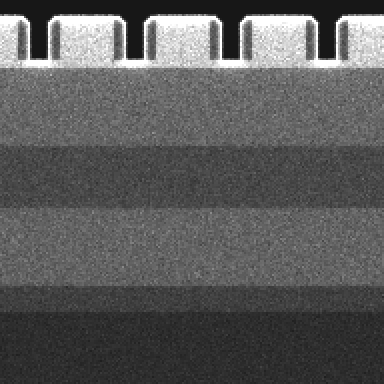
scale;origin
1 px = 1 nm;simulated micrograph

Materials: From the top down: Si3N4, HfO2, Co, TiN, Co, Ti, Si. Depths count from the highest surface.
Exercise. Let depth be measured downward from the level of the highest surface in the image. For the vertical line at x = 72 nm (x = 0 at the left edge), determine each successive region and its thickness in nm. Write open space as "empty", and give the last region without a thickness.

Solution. HfO2 52, Co 78, TiN 62, Co 78, Ti 26, Si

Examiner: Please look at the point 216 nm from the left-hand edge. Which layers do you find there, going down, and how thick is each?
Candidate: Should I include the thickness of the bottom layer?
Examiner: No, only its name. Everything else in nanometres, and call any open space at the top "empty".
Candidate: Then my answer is empty 2, Si3N4 42, HfO2 8, Co 78, TiN 62, Co 78, Ti 26, Si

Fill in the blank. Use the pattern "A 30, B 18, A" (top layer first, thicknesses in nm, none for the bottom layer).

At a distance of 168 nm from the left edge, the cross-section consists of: HfO2 52, Co 78, TiN 62, Co 78, Ti 26, Si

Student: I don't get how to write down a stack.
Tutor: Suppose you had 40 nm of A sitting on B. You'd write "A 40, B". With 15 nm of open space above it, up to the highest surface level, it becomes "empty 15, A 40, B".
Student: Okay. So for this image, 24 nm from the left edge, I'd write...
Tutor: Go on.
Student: empty 2, Si3N4 42, HfO2 8, Co 78, TiN 62, Co 78, Ti 26, Si